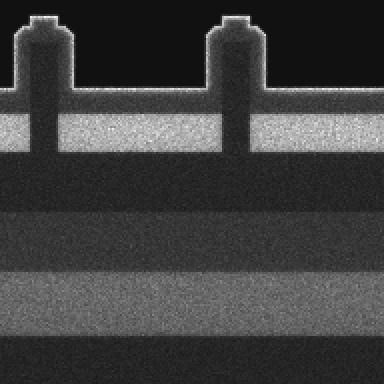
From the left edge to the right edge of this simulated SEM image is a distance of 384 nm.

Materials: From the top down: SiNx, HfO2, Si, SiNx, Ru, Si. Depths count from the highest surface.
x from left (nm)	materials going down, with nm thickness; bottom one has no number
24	empty 10, SiNx 88, HfO2 38, Si 60, SiNx 60, Ru 64, Si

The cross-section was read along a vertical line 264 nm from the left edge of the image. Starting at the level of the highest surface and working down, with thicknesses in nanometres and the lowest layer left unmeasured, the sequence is empty 18, SiNx 80, HfO2 38, Si 60, SiNx 60, Ru 64, Si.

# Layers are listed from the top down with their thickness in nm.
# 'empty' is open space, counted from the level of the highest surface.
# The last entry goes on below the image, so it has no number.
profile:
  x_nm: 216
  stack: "empty 10, SiNx 88, HfO2 38, Si 60, SiNx 60, Ru 64, Si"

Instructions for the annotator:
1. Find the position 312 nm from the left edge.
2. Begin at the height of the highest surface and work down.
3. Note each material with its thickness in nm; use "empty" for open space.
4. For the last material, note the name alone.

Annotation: empty 72, SiNx 26, HfO2 38, Si 60, SiNx 60, Ru 64, Si